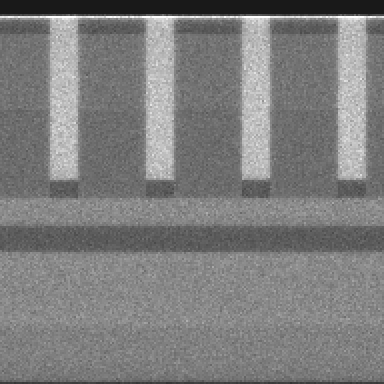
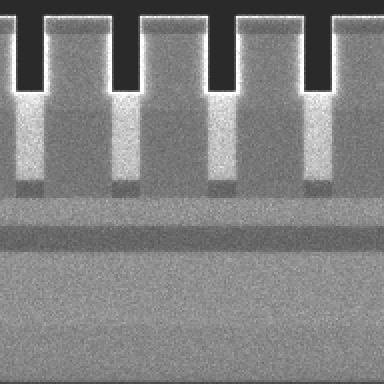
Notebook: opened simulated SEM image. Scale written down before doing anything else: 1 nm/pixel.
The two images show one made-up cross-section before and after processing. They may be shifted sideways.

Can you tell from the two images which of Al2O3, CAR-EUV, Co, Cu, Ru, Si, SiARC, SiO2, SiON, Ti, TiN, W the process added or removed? Yes, it removed W.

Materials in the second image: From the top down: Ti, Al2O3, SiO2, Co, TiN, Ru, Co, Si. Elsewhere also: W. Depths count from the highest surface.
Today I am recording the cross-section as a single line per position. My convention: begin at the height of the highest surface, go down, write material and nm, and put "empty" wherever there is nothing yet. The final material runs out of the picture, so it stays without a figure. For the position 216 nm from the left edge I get empty 76, W 88, Ti 18, Co 28, TiN 26, Ru 74, Co 56, Si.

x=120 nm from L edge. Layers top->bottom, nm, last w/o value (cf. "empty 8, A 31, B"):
empty 76, W 88, Ti 18, Co 28, TiN 26, Ru 74, Co 56, Si